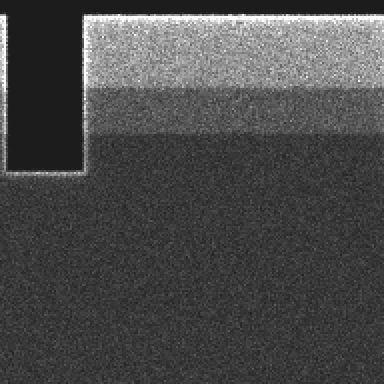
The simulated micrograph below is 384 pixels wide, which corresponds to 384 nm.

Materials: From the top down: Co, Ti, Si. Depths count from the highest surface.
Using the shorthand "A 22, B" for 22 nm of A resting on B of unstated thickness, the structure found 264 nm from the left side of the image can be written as Co 72, Ti 46, Si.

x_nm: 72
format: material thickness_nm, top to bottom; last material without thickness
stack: empty 156, Si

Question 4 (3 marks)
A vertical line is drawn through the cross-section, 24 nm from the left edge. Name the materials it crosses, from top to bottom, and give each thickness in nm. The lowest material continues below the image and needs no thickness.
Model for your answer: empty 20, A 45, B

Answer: empty 156, Si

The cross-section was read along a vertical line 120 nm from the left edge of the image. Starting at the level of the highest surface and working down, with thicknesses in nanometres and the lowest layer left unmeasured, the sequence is Co 72, Ti 46, Si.